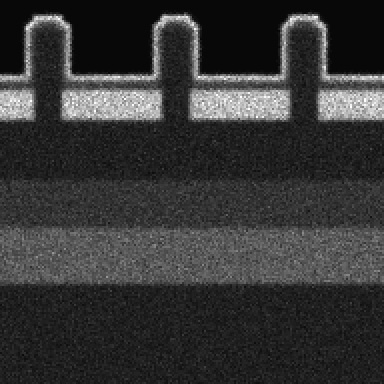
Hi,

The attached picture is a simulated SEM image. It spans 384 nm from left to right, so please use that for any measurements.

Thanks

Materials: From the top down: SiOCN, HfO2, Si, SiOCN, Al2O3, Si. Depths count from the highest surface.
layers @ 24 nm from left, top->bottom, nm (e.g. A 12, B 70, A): empty 60, SiOCN 14, HfO2 30, Si 60, SiOCN 48, Al2O3 56, Si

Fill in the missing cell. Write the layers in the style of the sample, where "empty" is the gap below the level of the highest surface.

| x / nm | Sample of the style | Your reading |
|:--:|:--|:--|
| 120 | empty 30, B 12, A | empty 60, SiOCN 14, HfO2 30, Si 60, SiOCN 48, Al2O3 56, Si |